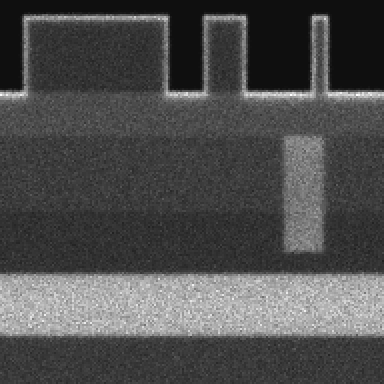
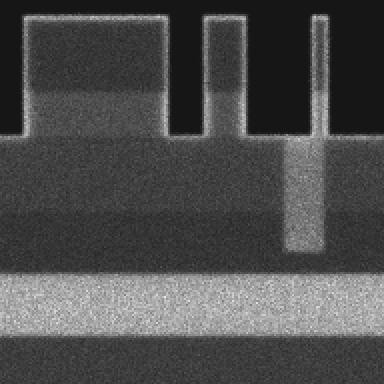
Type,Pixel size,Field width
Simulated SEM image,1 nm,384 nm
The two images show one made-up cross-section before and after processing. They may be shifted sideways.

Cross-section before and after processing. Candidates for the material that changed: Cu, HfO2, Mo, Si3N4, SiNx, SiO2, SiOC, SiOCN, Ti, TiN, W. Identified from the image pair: SiO2 (removed).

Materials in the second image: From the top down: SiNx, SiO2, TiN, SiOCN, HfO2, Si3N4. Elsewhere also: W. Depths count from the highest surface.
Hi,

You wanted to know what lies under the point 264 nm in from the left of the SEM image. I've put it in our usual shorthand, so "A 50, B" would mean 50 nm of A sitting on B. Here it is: empty 120, TiN 76, SiOCN 62, HfO2 62, Si3N4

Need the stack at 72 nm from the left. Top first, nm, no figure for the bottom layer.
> SiNx 76, SiO2 44, TiN 76, SiOCN 62, HfO2 62, Si3N4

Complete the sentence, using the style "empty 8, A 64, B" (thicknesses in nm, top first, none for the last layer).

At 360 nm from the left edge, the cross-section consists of empty 120, TiN 76, SiOCN 62, HfO2 62, Si3N4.